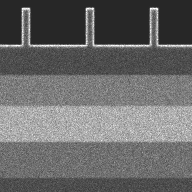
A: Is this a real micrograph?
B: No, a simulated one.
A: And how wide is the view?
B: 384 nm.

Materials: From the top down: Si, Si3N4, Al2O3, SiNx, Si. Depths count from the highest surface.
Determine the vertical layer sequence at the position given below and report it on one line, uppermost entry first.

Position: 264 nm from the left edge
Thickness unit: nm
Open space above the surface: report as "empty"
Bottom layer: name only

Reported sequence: empty 74, Si 60, Si3N4 62, Al2O3 72, SiNx 72, Si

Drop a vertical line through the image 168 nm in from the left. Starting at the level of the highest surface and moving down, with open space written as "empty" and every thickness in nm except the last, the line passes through empty 74, Si 60, Si3N4 62, Al2O3 72, SiNx 72, Si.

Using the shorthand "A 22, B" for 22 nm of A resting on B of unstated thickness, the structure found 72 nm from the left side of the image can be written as empty 74, Si 60, Si3N4 62, Al2O3 72, SiNx 72, Si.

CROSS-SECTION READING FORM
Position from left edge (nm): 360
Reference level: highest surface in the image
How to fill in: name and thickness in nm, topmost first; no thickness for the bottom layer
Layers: empty 74, Si 60, Si3N4 62, Al2O3 72, SiNx 72, Si